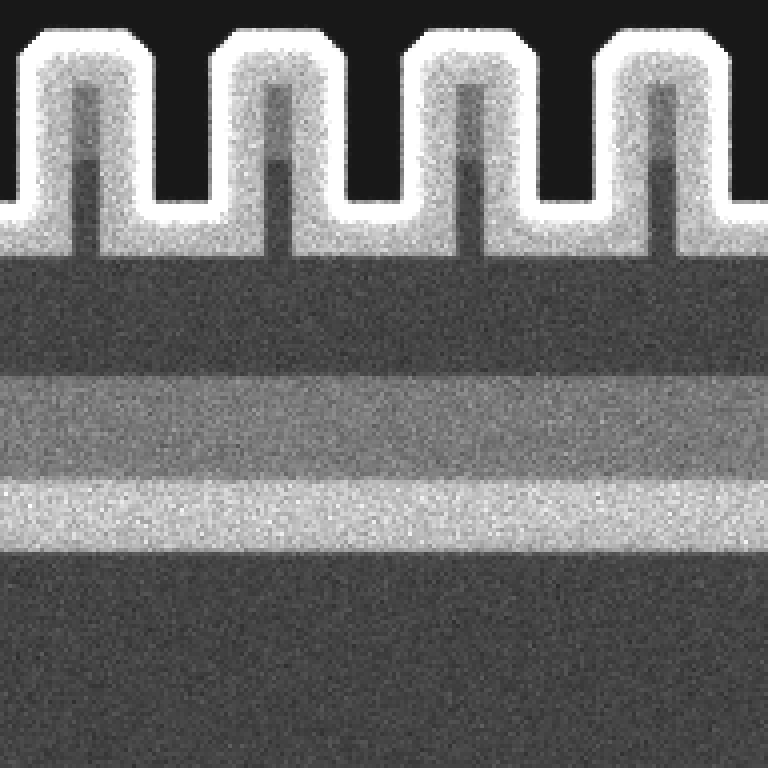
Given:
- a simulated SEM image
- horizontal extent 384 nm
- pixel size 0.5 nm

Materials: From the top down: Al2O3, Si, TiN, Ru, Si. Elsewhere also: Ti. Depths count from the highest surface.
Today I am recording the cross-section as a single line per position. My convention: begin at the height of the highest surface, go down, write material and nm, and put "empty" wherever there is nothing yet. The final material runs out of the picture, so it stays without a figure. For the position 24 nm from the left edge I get Al2O3 112, Si 60, TiN 52, Ru 36, Si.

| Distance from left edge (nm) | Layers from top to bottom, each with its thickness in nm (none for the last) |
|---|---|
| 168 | empty 10, Al2O3 102, Si 60, TiN 52, Ru 36, Si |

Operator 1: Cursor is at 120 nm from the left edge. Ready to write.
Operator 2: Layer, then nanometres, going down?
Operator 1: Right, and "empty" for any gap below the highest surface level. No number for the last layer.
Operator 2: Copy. Al2O3 112, Si 60, TiN 52, Ru 36, Si